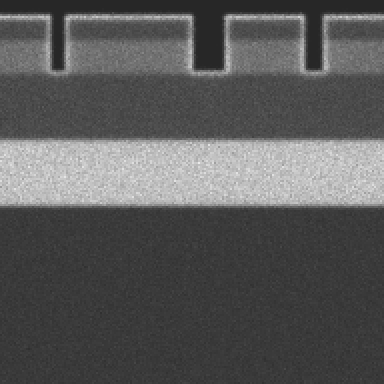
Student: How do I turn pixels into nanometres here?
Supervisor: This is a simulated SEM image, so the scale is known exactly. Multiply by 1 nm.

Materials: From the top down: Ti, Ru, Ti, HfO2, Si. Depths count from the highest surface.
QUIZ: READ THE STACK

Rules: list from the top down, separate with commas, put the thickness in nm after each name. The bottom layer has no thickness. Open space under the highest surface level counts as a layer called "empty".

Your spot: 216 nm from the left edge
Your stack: empty 56, Ti 68, HfO2 66, Si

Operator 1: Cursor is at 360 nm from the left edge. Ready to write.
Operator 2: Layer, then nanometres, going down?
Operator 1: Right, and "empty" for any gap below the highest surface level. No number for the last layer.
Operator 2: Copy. Ti 24, Ru 34, Ti 66, HfO2 66, Si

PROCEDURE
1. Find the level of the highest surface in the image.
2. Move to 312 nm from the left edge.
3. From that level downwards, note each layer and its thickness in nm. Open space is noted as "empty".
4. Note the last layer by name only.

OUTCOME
empty 56, Ti 68, HfO2 66, Si